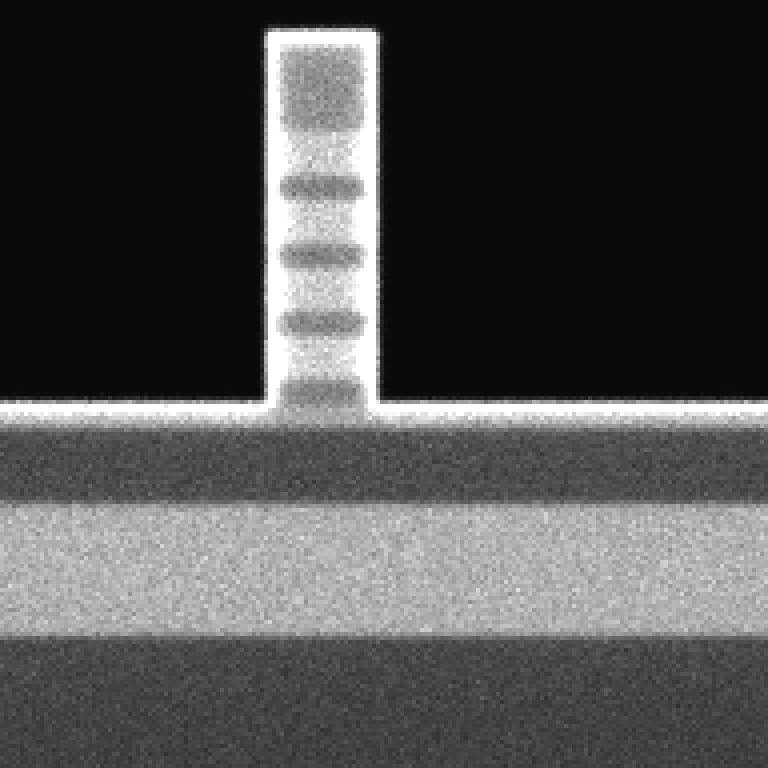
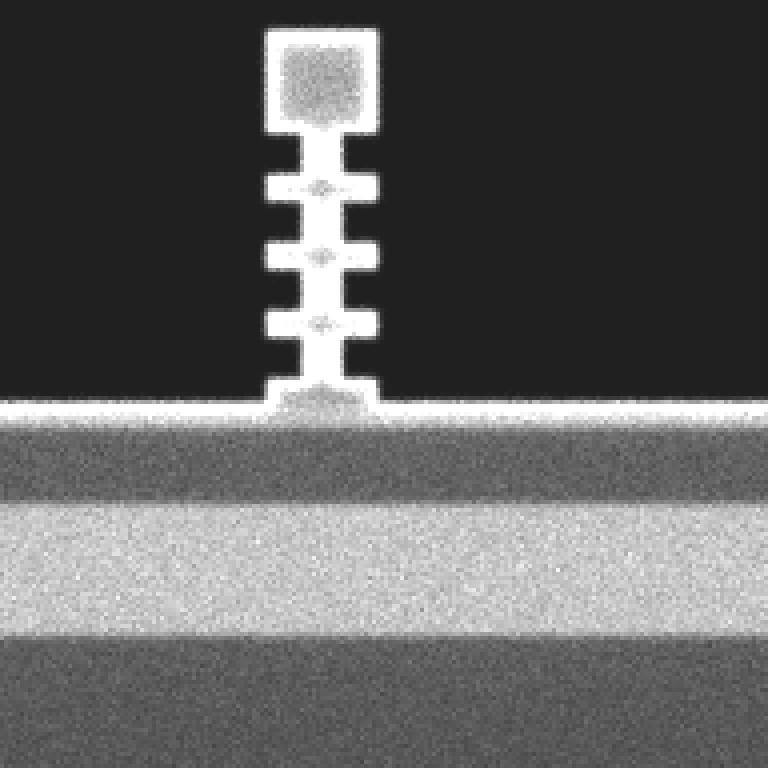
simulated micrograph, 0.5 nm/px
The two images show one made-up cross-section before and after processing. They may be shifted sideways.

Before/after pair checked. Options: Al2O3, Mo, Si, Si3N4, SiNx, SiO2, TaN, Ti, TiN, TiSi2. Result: removed Al2O3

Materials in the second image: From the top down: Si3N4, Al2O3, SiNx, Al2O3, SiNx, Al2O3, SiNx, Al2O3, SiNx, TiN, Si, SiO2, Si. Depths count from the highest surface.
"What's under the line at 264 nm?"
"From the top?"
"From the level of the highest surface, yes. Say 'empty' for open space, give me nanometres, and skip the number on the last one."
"empty 186, TiN 12, Si 38, SiO2 66, Si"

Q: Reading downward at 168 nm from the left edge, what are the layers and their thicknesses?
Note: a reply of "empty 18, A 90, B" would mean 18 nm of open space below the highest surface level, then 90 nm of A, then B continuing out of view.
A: Si3N4 50, Al2O3 22, SiNx 12, Al2O3 22, SiNx 12, Al2O3 22, SiNx 12, Al2O3 22, SiNx 12, TiN 12, Si 38, SiO2 66, Si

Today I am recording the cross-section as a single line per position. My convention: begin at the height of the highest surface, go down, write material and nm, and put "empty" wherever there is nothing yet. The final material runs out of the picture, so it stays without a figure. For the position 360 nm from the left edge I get empty 186, TiN 12, Si 38, SiO2 66, Si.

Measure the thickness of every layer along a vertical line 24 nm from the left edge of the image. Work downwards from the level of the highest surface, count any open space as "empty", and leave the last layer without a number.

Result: empty 186, TiN 12, Si 38, SiO2 66, Si